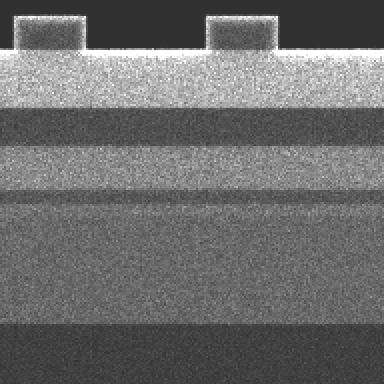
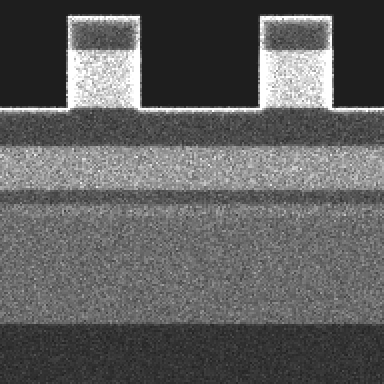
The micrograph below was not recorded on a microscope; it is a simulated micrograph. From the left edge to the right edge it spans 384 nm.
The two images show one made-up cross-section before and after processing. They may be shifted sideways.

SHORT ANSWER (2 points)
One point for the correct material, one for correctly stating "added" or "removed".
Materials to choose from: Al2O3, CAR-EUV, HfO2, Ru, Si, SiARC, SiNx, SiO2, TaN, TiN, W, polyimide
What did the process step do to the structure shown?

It removed HfO2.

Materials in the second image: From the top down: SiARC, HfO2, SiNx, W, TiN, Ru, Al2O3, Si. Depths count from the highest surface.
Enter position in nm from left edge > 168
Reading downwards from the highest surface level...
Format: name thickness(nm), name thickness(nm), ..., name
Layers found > empty 92, SiNx 38, W 44, TiN 14, Ru 12, Al2O3 108, Si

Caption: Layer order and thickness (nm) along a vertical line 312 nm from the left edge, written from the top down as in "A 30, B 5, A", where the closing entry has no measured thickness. SiARC 34, HfO2 58, SiNx 38, W 44, TiN 14, Ru 12, Al2O3 108, Si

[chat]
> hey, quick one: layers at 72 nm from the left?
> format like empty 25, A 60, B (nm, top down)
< SiARC 34, HfO2 58, SiNx 38, W 44, TiN 14, Ru 12, Al2O3 108, Si